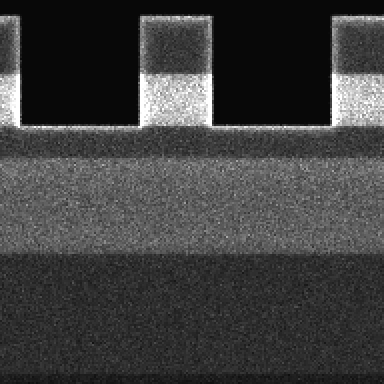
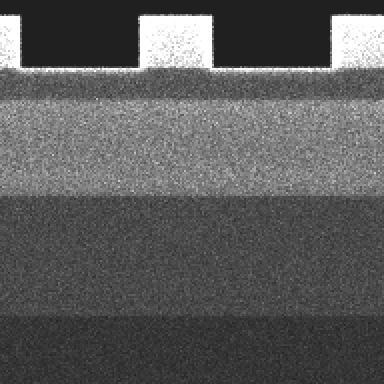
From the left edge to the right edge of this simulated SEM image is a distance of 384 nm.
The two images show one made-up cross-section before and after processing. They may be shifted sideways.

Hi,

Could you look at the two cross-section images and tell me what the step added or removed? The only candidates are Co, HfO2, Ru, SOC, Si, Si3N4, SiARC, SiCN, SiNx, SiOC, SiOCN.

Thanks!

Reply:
removed SOC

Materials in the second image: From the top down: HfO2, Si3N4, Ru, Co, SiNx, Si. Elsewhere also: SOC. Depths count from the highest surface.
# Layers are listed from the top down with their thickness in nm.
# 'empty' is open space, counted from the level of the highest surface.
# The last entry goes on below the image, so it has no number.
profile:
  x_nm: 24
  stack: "empty 52, Si3N4 32, Ru 86, Co 10, SiNx 120, Si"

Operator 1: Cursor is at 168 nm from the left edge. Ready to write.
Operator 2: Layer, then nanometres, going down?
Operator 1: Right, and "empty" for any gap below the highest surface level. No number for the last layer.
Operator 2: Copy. HfO2 52, Si3N4 32, Ru 86, Co 10, SiNx 120, Si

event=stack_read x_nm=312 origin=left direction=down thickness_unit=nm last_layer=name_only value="empty 52, Si3N4 32, Ru 86, Co 10, SiNx 120, Si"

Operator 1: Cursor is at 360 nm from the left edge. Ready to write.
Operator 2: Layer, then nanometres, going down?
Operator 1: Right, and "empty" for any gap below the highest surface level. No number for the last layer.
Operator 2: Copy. HfO2 52, Si3N4 32, Ru 86, Co 10, SiNx 120, Si